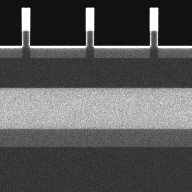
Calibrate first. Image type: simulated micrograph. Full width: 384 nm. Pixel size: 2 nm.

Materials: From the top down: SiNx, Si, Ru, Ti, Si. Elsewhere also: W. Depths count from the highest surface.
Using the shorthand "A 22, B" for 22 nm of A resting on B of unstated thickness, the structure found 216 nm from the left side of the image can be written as empty 76, SiNx 24, Si 60, Ru 82, Ti 36, Si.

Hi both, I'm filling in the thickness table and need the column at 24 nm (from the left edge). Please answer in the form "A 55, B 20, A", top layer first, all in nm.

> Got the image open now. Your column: empty 76, SiNx 24, Si 60, Ru 82, Ti 36, Si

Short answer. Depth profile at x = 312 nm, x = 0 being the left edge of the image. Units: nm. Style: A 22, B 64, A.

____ W 46, Si 114, Ru 82, Ti 36, Si